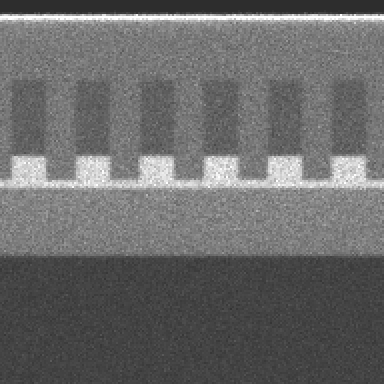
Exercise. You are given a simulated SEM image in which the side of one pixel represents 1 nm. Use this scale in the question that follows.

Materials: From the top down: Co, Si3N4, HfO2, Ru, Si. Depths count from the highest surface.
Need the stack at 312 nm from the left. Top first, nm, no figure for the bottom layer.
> Co 164, HfO2 8, Ru 68, Si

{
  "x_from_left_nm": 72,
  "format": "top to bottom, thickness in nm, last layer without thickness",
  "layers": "Co 164, HfO2 8, Ru 68, Si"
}